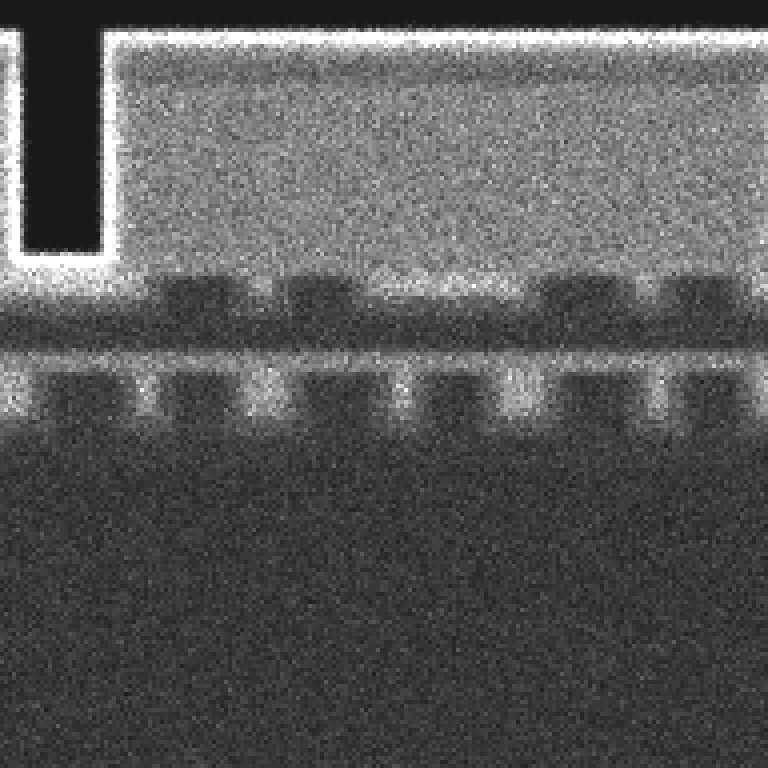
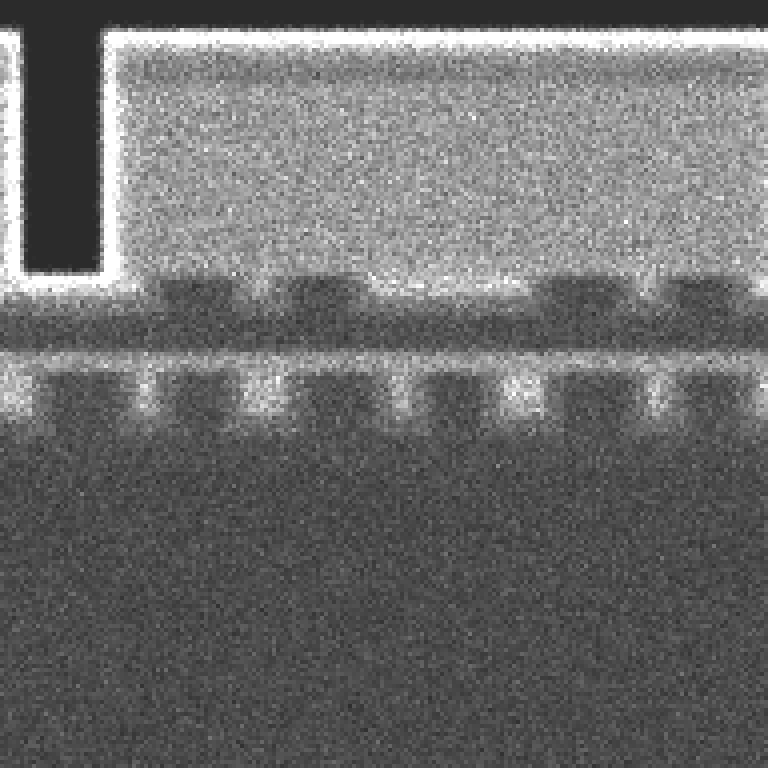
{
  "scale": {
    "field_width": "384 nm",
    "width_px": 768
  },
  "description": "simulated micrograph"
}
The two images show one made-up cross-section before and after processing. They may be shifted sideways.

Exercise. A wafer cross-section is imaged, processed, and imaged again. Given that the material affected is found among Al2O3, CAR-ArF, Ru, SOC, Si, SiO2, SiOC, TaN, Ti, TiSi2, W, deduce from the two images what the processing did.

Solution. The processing removed Al2O3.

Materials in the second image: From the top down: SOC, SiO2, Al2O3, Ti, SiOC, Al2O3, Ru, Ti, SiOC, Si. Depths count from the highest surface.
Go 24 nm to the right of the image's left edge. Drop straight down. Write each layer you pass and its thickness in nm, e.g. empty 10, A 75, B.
empty 122, Ru 10, Ti 10, SiOC 18, Al2O3 10, Ti 32, SiOC 16, Si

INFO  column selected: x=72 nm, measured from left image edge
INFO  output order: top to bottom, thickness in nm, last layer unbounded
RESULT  SOC 26, SiO2 86, Al2O3 10, Ti 20, SiOC 18, Al2O3 10, Ru 22, Ti 10, SiOC 16, Si